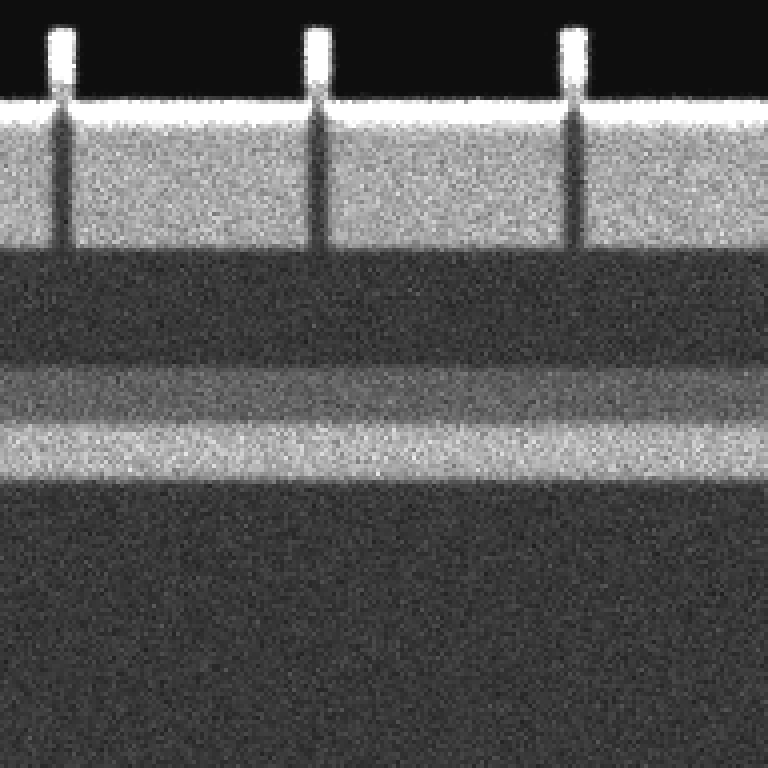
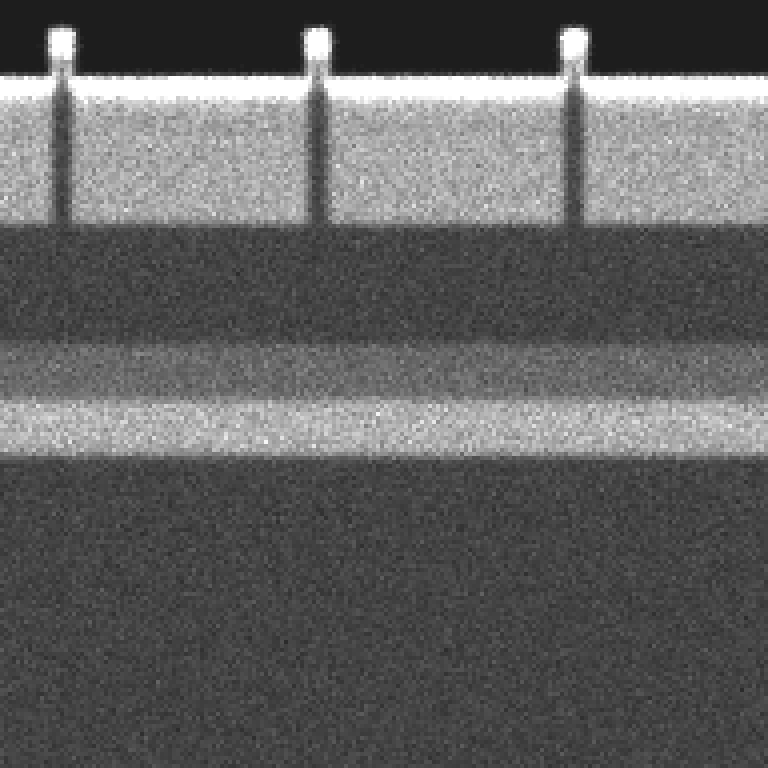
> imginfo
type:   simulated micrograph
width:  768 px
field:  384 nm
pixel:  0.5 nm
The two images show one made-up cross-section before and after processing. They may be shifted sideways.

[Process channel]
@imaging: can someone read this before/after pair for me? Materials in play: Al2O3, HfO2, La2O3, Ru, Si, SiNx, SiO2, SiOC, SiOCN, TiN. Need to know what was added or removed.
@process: Ru removed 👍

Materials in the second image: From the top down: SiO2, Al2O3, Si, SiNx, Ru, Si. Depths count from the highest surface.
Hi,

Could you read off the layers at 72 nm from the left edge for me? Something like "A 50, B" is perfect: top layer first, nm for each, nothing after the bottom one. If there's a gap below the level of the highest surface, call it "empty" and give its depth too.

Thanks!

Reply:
empty 24, SiO2 28, Al2O3 44, Si 60, SiNx 28, Ru 28, Si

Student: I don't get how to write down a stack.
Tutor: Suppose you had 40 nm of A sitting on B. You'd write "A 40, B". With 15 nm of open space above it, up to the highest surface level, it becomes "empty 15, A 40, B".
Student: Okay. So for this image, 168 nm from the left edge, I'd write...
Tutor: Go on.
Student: empty 24, SiO2 28, Al2O3 44, Si 60, SiNx 28, Ru 28, Si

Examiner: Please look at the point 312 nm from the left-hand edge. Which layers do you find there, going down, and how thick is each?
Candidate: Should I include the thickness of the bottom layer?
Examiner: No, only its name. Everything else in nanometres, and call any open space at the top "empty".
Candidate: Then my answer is empty 24, SiO2 28, Al2O3 44, Si 60, SiNx 28, Ru 28, Si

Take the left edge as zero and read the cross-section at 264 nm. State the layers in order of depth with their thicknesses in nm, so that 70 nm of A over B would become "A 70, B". empty 24, SiO2 28, Al2O3 44, Si 60, SiNx 28, Ru 28, Si